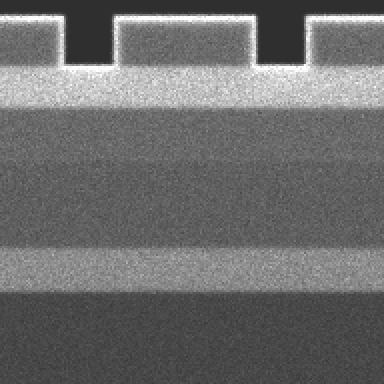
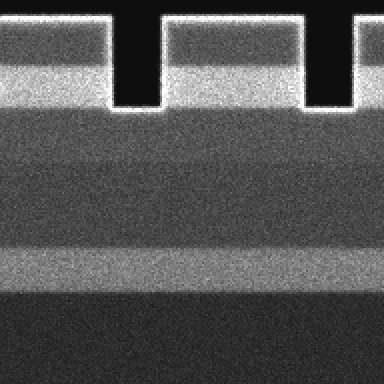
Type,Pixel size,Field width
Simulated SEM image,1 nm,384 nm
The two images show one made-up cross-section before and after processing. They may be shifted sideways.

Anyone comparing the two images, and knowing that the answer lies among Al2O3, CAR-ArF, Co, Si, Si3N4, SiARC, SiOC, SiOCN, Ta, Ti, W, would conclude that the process removed W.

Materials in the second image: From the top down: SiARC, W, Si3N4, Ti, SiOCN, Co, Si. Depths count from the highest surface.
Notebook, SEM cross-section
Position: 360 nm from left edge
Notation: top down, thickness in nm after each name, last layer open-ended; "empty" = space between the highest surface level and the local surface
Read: SiARC 50, W 42, Si3N4 54, Ti 20, SiOCN 66, Co 44, Si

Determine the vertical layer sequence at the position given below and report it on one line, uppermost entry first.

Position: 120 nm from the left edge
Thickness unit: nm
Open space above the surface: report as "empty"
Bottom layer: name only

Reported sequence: empty 92, Si3N4 54, Ti 20, SiOCN 66, Co 44, Si